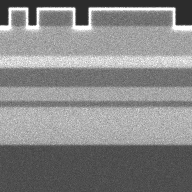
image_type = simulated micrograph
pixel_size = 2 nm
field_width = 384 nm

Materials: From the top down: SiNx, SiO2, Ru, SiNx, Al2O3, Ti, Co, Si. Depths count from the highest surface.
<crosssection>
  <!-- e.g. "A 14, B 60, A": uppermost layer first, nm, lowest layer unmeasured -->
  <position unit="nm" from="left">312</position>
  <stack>SiNx 36, SiO2 60, Ru 24, SiNx 38, Al2O3 28, Ti 12, Co 76, Si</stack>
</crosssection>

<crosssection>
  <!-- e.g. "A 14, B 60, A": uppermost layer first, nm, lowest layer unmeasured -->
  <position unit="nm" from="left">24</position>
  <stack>SiNx 36, SiO2 60, Ru 24, SiNx 38, Al2O3 28, Ti 12, Co 76, Si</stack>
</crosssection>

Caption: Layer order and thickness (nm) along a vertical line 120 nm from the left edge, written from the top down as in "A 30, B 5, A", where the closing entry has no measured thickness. SiNx 36, SiO2 60, Ru 24, SiNx 38, Al2O3 28, Ti 12, Co 76, Si